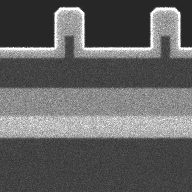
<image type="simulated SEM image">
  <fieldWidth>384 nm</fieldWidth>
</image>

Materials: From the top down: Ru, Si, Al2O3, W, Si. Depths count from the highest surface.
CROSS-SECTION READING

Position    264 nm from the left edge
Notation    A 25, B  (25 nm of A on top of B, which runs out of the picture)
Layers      empty 80, Ru 20, Si 60, Al2O3 56, W 44, Si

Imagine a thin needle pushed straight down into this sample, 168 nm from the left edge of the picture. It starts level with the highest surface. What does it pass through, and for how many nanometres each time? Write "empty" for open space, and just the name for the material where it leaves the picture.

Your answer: empty 80, Ru 20, Si 60, Al2O3 56, W 44, Si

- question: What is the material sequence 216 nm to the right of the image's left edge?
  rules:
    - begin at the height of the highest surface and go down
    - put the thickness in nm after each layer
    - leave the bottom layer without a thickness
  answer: empty 80, Ru 20, Si 60, Al2O3 56, W 44, Si